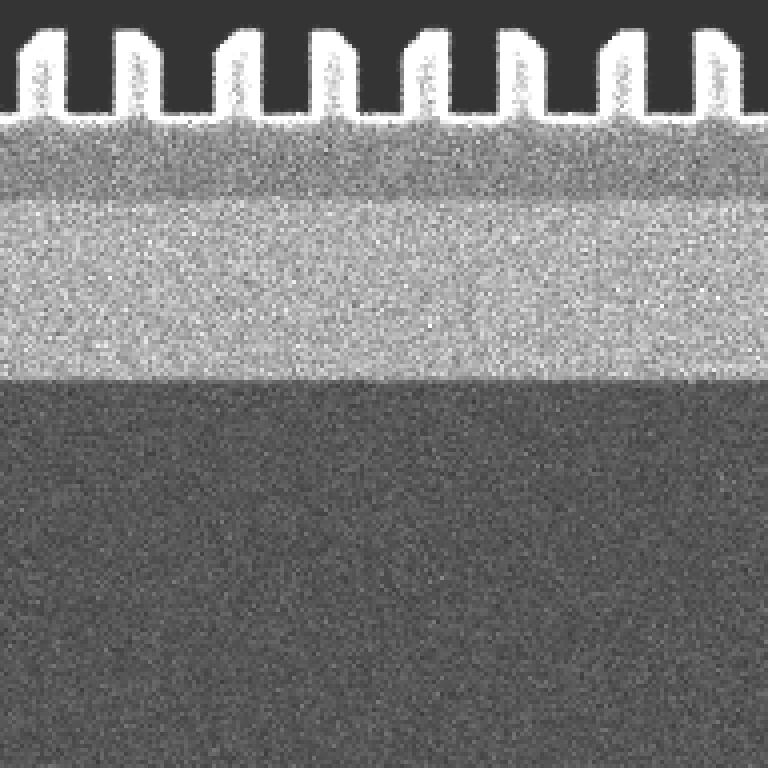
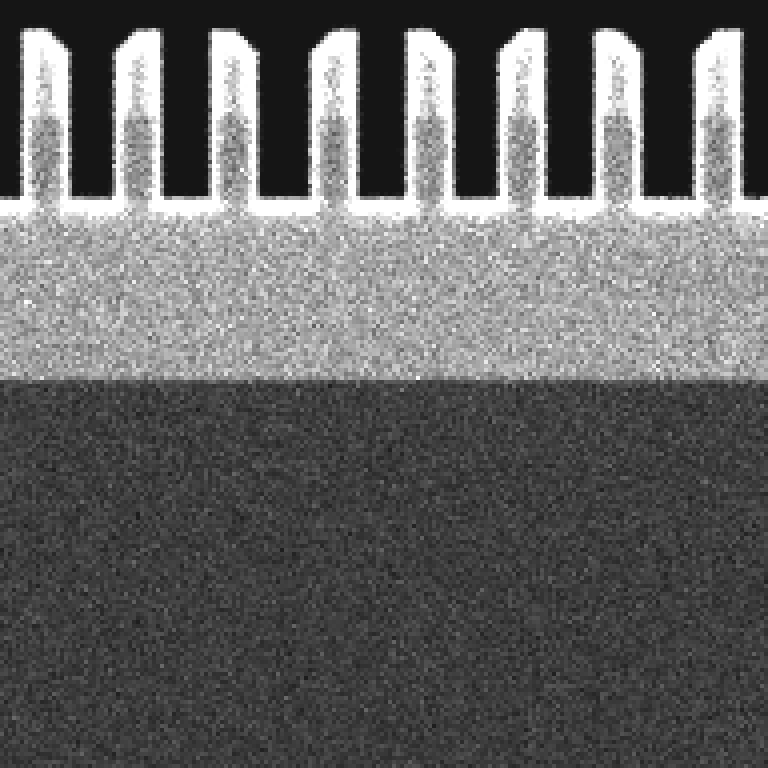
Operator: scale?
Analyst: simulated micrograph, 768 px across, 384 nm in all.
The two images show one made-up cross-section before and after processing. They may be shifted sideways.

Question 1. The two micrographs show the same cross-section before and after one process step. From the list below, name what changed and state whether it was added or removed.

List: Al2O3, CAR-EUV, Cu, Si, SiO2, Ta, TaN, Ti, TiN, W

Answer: TiN, removed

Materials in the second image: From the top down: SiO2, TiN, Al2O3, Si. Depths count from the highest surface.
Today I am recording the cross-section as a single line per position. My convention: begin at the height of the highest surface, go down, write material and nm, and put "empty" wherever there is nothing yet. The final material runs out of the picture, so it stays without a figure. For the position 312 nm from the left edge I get empty 4, SiO2 38, TiN 42, Al2O3 90, Si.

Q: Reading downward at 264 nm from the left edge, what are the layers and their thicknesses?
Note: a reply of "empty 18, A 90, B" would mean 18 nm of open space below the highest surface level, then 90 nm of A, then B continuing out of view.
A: SiO2 42, TiN 42, Al2O3 90, Si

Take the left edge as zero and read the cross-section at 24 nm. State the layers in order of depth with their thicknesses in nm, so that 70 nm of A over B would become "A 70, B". empty 2, SiO2 40, TiN 42, Al2O3 90, Si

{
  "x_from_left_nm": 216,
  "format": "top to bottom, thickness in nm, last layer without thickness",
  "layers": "empty 2, SiO2 40, TiN 42, Al2O3 90, Si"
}